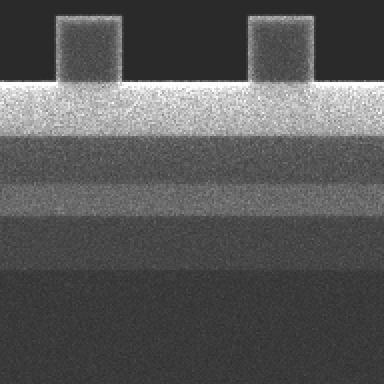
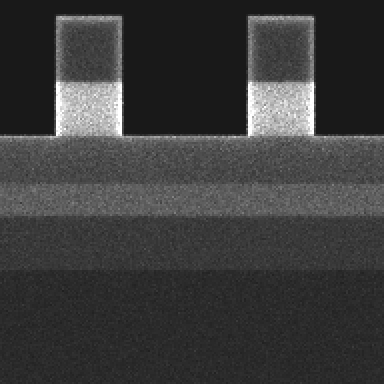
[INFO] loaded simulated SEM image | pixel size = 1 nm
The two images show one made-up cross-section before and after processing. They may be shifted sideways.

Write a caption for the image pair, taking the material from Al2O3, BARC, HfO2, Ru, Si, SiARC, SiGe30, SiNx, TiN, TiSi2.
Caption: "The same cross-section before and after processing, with HfO2 removed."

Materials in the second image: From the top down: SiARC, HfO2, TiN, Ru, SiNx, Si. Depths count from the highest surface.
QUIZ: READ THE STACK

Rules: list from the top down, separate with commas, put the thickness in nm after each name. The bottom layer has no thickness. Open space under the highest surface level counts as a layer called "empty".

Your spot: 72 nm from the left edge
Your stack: SiARC 66, HfO2 54, TiN 48, Ru 32, SiNx 54, Si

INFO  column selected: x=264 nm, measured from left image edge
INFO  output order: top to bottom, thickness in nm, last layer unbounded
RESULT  SiARC 66, HfO2 54, TiN 48, Ru 32, SiNx 54, Si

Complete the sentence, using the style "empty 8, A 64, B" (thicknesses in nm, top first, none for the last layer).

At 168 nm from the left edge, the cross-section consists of empty 120, TiN 48, Ru 32, SiNx 54, Si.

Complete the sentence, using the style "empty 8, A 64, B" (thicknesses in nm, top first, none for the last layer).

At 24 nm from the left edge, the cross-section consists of empty 120, TiN 48, Ru 32, SiNx 54, Si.